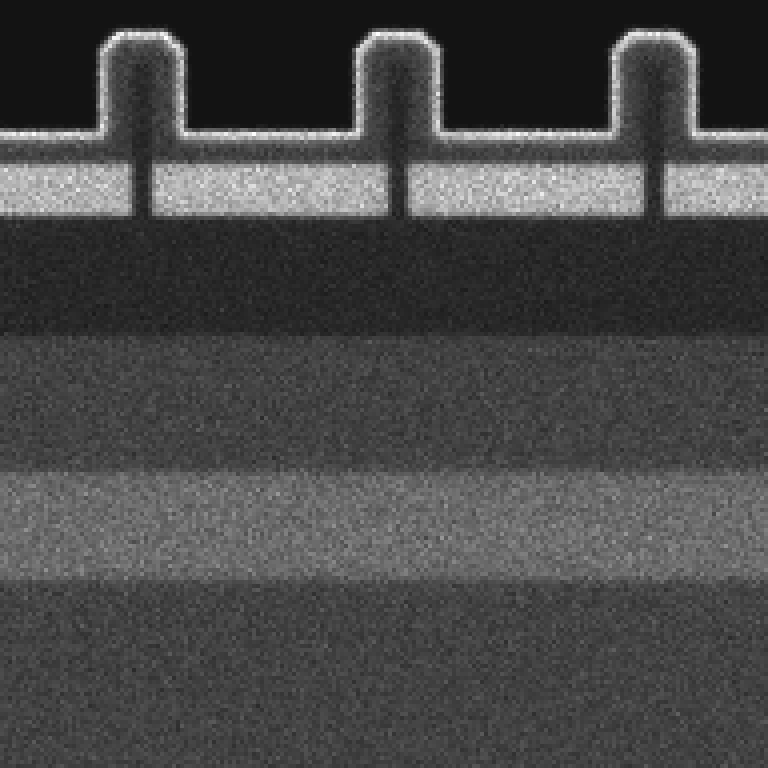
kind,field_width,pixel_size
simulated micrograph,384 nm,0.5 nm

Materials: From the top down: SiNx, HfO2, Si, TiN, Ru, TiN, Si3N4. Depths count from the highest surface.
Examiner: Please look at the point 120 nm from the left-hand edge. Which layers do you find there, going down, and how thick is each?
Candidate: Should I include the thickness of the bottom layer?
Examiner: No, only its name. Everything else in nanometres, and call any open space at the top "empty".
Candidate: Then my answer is empty 50, SiNx 16, HfO2 26, Si 60, TiN 68, Ru 54, TiN 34, Si3N4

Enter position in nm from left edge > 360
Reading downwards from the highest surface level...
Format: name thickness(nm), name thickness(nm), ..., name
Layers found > empty 50, SiNx 16, HfO2 26, Si 60, TiN 68, Ru 54, TiN 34, Si3N4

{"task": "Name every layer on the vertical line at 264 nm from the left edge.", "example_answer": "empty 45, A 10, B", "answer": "empty 50, SiNx 16, HfO2 26, Si 60, TiN 68, Ru 54, TiN 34, Si3N4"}